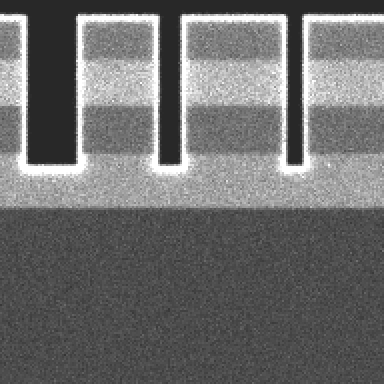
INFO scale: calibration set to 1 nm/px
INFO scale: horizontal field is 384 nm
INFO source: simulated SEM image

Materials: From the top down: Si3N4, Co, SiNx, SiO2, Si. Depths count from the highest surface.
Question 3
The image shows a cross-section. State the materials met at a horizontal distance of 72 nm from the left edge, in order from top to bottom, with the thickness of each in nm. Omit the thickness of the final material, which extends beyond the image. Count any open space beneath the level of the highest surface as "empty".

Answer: empty 150, SiO2 42, Si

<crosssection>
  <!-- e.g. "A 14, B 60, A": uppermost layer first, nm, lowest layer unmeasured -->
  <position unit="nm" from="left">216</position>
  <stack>Si3N4 44, Co 46, SiNx 48, SiO2 54, Si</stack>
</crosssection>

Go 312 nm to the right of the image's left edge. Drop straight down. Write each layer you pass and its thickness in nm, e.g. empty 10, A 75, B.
Si3N4 44, Co 46, SiNx 48, SiO2 54, Si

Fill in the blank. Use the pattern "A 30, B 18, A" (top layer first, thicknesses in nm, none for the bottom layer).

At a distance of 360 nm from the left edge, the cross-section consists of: Si3N4 44, Co 46, SiNx 48, SiO2 54, Si